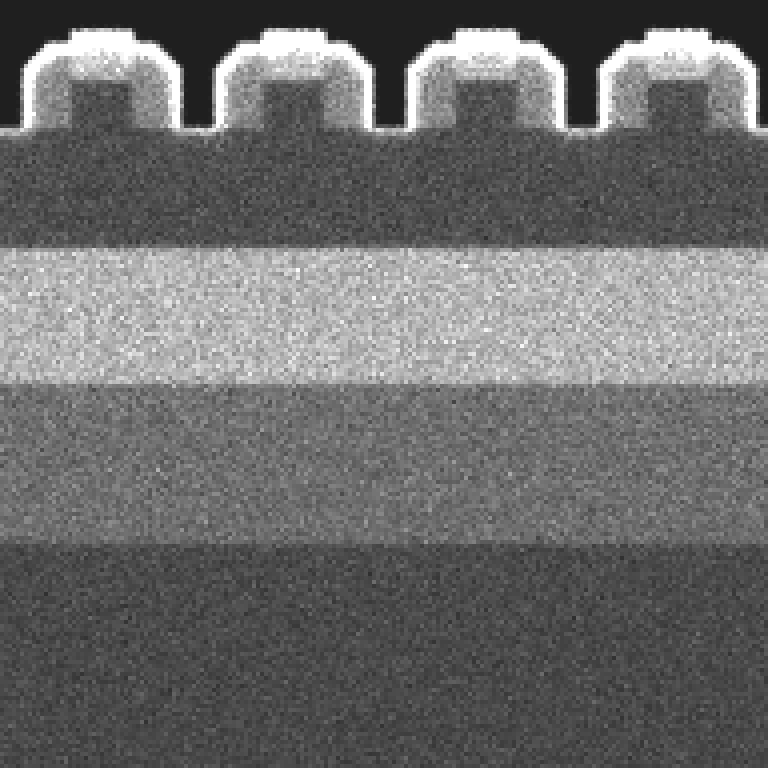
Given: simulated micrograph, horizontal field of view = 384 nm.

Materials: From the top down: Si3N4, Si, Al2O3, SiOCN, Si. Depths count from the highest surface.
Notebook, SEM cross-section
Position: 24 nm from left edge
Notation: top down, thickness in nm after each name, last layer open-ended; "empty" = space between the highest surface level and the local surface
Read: empty 6, Si3N4 42, Si 60, Al2O3 68, SiOCN 80, Si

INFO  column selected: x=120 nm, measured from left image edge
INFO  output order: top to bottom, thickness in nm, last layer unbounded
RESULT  empty 6, Si3N4 42, Si 60, Al2O3 68, SiOCN 80, Si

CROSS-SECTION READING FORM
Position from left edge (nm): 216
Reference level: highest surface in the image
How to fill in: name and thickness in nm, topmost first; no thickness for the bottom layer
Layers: empty 6, Si3N4 42, Si 60, Al2O3 68, SiOCN 80, Si